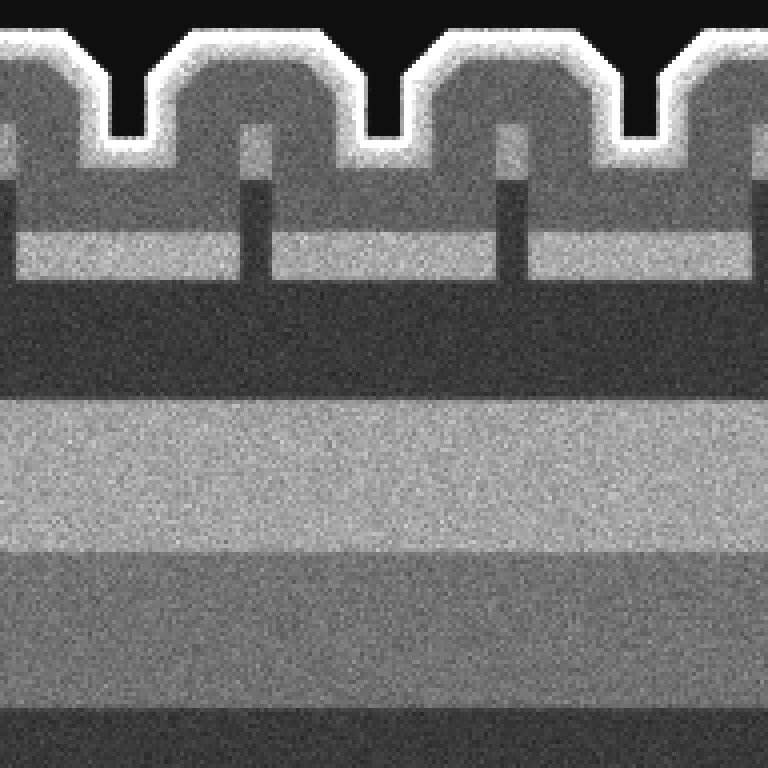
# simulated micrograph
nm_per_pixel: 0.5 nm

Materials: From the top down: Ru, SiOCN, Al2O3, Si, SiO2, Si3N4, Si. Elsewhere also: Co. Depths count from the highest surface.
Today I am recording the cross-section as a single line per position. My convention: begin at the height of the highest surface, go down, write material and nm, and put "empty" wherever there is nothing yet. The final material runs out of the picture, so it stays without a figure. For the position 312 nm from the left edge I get empty 54, Ru 14, SiOCN 32, Al2O3 24, Si 60, SiO2 76, Si3N4 78, Si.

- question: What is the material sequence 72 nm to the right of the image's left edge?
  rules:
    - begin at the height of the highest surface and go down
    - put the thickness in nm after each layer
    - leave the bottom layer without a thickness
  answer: empty 54, Ru 14, SiOCN 32, Al2O3 24, Si 60, SiO2 76, Si3N4 78, Si